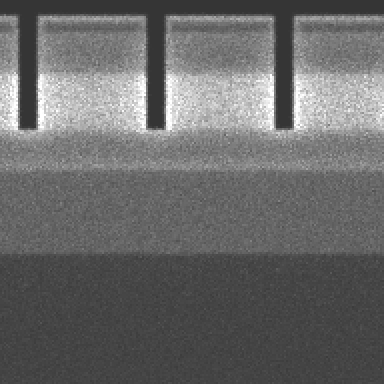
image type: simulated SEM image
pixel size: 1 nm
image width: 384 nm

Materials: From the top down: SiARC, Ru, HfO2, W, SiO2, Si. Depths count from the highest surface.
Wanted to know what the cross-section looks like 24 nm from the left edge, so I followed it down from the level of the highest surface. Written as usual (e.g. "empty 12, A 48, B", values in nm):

empty 114, W 40, SiO2 84, Si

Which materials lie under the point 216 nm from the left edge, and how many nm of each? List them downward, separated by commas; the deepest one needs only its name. SiARC 16, Ru 42, HfO2 56, W 40, SiO2 84, Si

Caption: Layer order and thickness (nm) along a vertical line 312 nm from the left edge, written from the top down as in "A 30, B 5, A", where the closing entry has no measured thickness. SiARC 16, Ru 42, HfO2 56, W 40, SiO2 84, Si